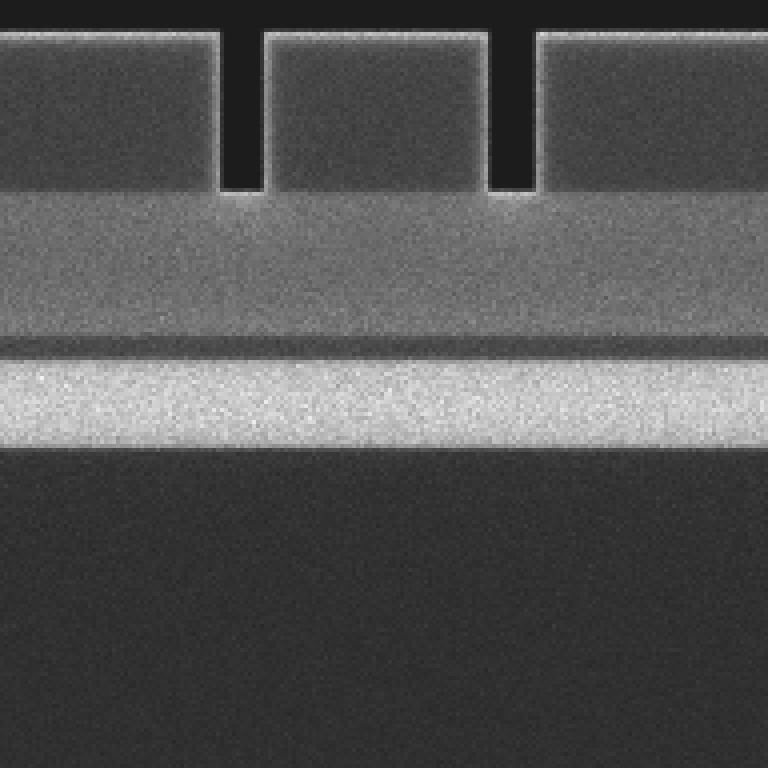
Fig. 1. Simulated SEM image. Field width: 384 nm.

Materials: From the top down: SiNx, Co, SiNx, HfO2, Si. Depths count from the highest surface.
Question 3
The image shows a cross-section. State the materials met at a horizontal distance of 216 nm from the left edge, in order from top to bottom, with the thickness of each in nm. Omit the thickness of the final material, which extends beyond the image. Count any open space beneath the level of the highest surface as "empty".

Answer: SiNx 80, Co 72, SiNx 12, HfO2 44, Si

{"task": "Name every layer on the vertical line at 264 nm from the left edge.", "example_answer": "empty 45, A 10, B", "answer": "empty 80, Co 72, SiNx 12, HfO2 44, Si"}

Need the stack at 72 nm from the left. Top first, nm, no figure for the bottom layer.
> SiNx 80, Co 72, SiNx 12, HfO2 44, Si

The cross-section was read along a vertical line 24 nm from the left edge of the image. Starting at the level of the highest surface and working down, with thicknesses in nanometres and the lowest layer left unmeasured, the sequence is SiNx 80, Co 72, SiNx 12, HfO2 44, Si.